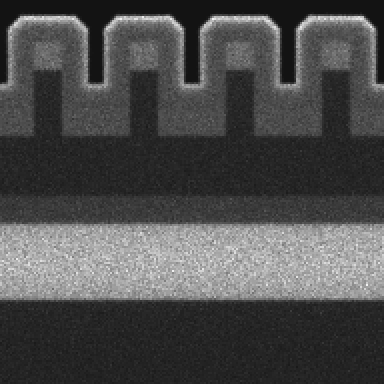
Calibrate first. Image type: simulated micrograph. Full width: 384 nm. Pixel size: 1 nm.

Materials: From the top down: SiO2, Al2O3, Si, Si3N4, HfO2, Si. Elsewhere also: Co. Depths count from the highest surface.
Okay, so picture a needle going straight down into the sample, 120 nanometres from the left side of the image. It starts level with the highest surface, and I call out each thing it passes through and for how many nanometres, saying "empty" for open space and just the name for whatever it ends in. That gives SiO2 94, Al2O3 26, Si 60, Si3N4 28, HfO2 76, Si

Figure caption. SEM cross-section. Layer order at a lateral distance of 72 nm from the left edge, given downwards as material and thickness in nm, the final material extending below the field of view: SiO2 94, Al2O3 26, Si 60, Si3N4 28, HfO2 76, Si